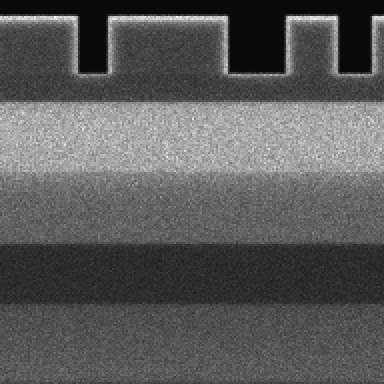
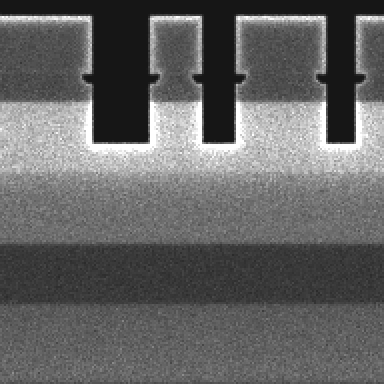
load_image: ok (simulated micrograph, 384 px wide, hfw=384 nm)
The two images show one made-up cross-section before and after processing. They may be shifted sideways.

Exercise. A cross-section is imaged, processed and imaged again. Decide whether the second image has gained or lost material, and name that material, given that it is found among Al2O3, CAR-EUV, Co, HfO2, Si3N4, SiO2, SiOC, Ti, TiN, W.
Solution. removed: HfO2 and TiN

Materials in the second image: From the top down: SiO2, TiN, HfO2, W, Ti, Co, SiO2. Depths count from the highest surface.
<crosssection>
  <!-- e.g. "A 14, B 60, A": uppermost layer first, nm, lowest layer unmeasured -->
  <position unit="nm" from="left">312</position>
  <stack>SiO2 58, TiN 28, HfO2 70, W 72, Ti 60, Co 78, SiO2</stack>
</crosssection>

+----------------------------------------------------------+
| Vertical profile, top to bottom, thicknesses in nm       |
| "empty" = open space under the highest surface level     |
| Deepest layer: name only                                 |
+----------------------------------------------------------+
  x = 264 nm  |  SiO2 58, TiN 28, HfO2 70, W 72, Ti 60, Co 78, SiO2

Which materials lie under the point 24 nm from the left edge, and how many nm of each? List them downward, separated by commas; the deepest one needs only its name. SiO2 58, TiN 28, HfO2 70, W 72, Ti 60, Co 78, SiO2